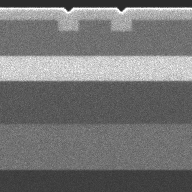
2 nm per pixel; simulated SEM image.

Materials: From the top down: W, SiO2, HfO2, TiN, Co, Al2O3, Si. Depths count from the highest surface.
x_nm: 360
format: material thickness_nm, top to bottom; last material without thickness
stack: W 24, SiO2 72, HfO2 50, TiN 86, Co 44, Al2O3 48, Si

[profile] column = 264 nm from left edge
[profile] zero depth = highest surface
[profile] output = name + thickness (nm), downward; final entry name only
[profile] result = W 24, SiO2 72, HfO2 50, TiN 86, Co 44, Al2O3 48, Si